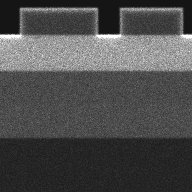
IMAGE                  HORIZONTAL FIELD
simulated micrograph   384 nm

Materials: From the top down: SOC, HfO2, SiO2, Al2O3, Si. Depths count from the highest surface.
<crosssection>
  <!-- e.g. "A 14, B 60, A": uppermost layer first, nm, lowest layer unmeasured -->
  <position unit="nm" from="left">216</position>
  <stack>empty 54, HfO2 72, SiO2 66, Al2O3 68, Si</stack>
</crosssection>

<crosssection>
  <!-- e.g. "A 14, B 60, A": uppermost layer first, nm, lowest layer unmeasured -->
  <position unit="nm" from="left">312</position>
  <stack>SOC 54, HfO2 72, SiO2 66, Al2O3 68, Si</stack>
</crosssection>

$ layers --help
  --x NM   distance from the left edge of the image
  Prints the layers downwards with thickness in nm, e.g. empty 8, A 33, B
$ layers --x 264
SOC 54, HfO2 72, SiO2 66, Al2O3 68, Si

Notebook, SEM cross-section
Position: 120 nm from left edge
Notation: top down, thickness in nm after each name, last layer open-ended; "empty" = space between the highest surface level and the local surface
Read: SOC 54, HfO2 72, SiO2 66, Al2O3 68, Si